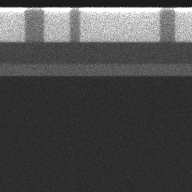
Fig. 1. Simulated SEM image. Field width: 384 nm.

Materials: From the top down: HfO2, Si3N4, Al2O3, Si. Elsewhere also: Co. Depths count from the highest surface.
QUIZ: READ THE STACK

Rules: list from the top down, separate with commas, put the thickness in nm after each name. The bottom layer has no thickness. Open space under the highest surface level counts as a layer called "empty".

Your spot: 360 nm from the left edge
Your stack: HfO2 68, Si3N4 44, Al2O3 24, Si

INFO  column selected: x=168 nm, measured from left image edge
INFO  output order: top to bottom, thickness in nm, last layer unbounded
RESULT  HfO2 68, Si3N4 44, Al2O3 24, Si